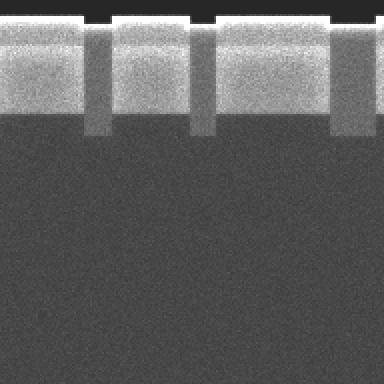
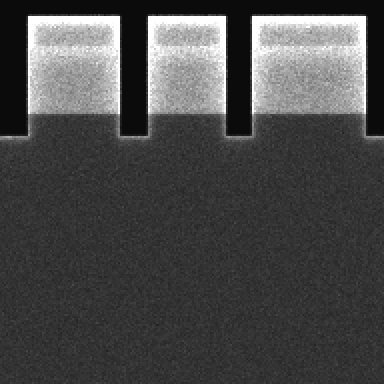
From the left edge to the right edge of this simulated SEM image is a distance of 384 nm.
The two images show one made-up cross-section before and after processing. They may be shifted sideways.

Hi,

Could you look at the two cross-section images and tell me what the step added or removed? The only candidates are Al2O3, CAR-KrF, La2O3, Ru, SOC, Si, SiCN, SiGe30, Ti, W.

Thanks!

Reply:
removed SOC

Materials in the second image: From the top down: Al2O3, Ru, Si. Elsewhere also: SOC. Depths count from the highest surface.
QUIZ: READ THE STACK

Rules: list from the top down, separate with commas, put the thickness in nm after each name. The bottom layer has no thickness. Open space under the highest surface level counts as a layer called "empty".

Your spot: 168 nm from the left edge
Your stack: Al2O3 30, Ru 68, Si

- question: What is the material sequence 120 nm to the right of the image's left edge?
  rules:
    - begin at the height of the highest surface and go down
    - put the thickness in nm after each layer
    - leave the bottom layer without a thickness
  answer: empty 120, Si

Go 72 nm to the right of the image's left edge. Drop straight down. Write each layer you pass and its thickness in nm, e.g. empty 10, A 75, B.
Al2O3 30, Ru 68, Si